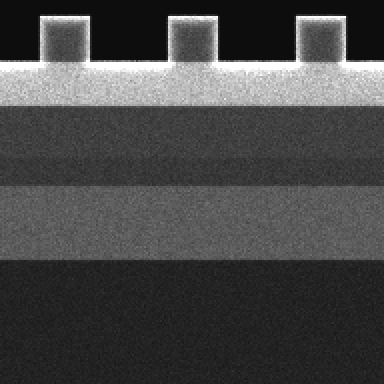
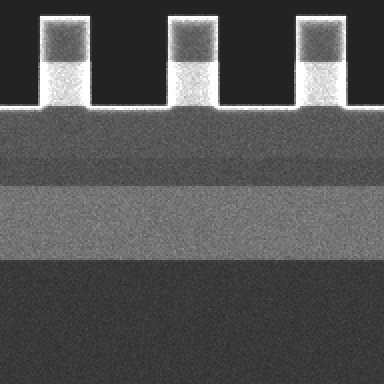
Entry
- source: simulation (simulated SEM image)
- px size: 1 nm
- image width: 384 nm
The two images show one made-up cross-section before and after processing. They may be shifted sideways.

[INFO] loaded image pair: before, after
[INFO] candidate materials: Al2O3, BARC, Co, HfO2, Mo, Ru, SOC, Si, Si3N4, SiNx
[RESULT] removed HfO2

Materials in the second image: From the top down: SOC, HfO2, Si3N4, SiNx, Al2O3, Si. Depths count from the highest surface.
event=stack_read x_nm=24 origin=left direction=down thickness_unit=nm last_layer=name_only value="empty 90, Si3N4 52, SiNx 28, Al2O3 74, Si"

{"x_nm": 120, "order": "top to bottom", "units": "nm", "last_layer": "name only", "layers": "empty 90, Si3N4 52, SiNx 28, Al2O3 74, Si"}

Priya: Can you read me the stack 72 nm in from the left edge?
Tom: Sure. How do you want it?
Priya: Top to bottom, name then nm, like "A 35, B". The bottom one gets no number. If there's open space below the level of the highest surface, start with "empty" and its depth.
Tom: SOC 46, HfO2 44, Si3N4 52, SiNx 28, Al2O3 74, Si